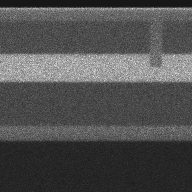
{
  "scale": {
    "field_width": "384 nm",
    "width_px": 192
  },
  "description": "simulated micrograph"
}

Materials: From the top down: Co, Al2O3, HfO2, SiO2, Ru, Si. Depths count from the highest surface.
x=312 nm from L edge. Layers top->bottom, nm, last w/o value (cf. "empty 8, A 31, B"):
Co 118, HfO2 30, SiO2 88, Ru 30, Si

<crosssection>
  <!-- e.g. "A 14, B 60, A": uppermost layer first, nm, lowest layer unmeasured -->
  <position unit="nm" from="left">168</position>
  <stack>Co 26, Al2O3 66, HfO2 56, SiO2 88, Ru 30, Si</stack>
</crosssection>